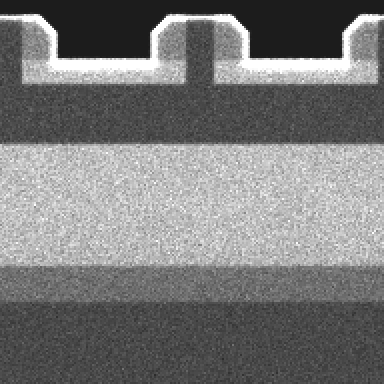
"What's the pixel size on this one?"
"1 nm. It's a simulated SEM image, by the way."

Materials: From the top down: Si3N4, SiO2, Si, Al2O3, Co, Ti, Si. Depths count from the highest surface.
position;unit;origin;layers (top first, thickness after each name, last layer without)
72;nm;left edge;empty 44, SiO2 24, Si 60, Al2O3 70, Co 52, Ti 36, Si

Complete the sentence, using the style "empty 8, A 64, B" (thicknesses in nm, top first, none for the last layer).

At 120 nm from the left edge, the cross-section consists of empty 44, SiO2 24, Si 60, Al2O3 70, Co 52, Ti 36, Si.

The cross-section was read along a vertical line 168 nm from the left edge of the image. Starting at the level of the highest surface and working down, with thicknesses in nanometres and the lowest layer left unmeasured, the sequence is Si3N4 44, SiO2 24, Si 60, Al2O3 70, Co 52, Ti 36, Si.